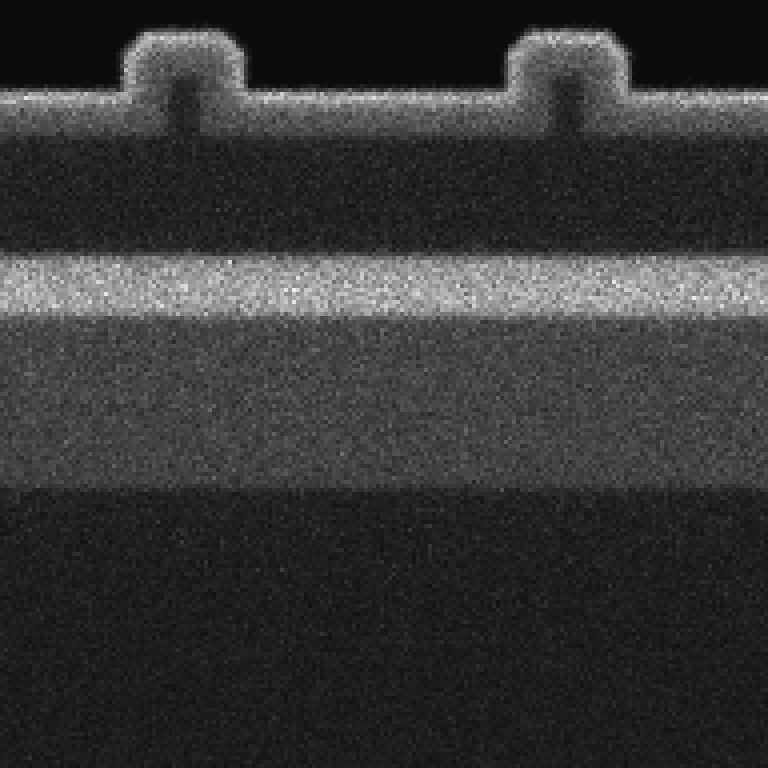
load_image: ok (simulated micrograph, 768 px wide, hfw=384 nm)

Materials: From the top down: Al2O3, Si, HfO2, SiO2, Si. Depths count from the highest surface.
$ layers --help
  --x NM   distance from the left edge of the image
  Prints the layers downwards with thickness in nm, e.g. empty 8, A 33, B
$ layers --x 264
Al2O3 52, Si 60, HfO2 30, SiO2 86, Si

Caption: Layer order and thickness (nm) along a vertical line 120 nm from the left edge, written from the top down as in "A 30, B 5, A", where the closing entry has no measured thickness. empty 10, Al2O3 42, Si 60, HfO2 30, SiO2 86, Si